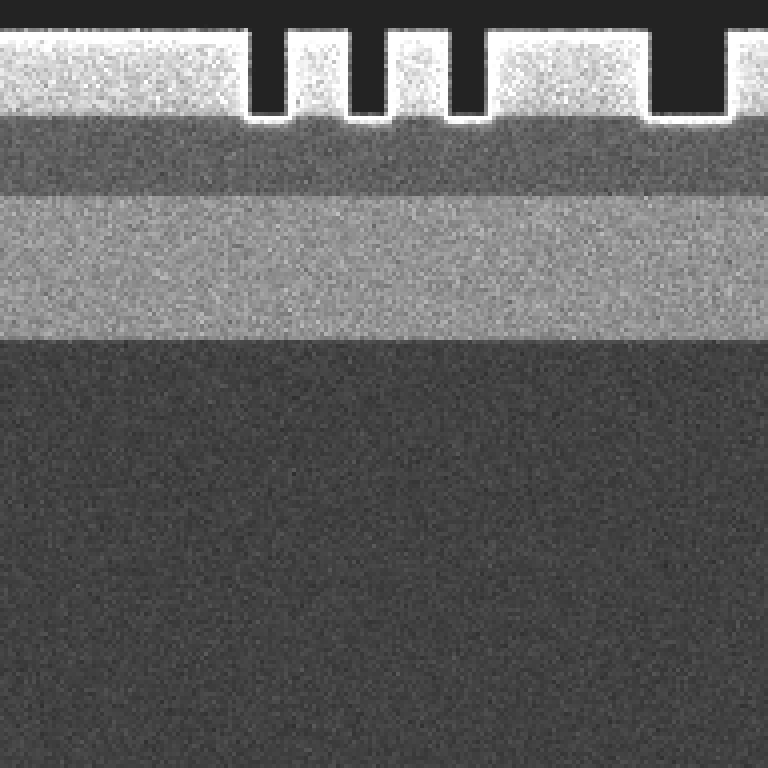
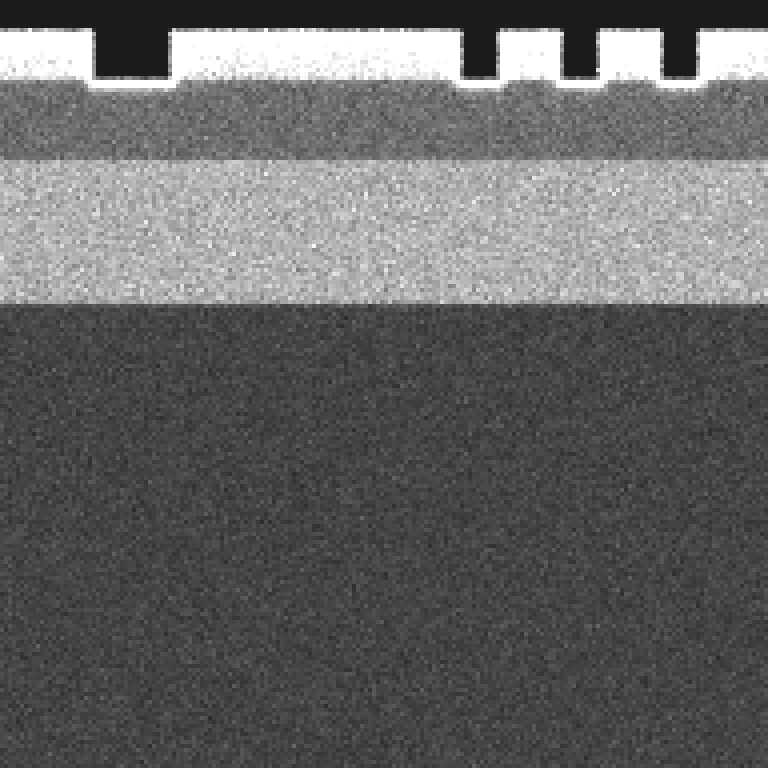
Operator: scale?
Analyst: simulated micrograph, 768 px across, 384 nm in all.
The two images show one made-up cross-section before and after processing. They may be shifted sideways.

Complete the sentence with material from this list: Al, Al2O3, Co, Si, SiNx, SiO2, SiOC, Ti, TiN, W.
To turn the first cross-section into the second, W must be removed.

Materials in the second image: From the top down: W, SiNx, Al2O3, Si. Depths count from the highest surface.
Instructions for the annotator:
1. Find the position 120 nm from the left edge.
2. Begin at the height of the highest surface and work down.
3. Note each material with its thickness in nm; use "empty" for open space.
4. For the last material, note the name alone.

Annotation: W 24, SiNx 40, Al2O3 72, Si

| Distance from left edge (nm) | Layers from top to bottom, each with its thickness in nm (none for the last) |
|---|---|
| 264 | W 24, SiNx 40, Al2O3 72, Si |